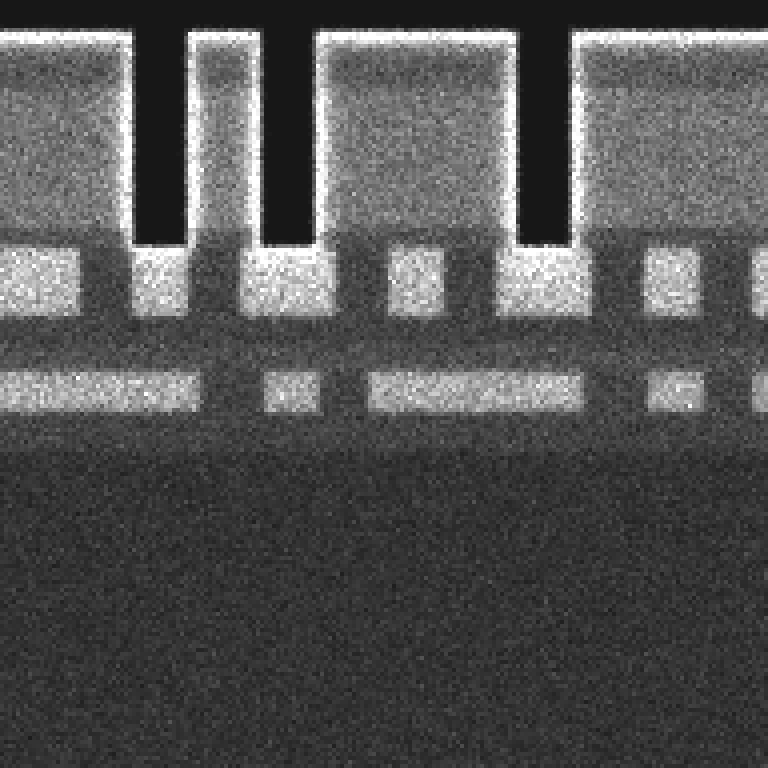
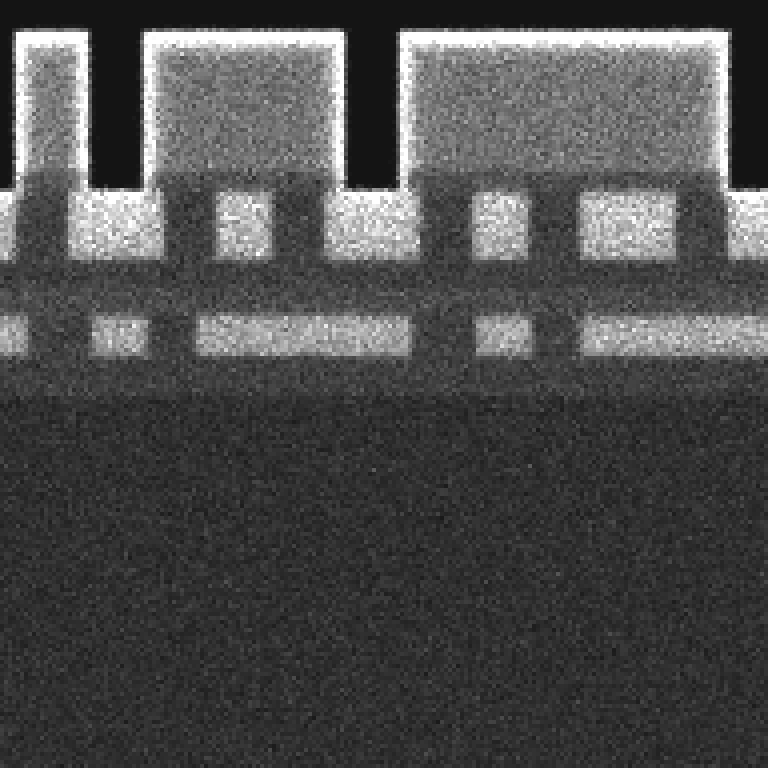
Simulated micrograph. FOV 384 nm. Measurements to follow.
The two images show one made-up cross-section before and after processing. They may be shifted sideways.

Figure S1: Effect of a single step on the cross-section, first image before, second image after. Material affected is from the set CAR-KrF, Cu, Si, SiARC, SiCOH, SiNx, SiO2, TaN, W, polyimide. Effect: removed SiARC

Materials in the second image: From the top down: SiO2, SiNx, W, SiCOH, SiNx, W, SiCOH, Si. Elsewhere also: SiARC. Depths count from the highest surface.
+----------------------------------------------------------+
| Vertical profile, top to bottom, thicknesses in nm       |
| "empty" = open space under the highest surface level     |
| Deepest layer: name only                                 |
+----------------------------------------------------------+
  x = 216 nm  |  SiO2 70, SiNx 10, SiCOH 48, SiNx 14, SiCOH 40, Si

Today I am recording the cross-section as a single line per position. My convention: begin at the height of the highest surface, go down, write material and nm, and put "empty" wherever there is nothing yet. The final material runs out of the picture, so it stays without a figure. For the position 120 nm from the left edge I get SiO2 70, SiNx 10, W 34, SiCOH 14, SiNx 14, W 20, SiCOH 20, Si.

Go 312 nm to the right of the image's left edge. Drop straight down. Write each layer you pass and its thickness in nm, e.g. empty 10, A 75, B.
SiO2 70, SiNx 10, W 34, SiCOH 14, SiNx 14, W 20, SiCOH 20, Si